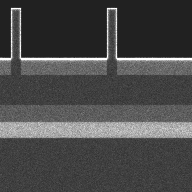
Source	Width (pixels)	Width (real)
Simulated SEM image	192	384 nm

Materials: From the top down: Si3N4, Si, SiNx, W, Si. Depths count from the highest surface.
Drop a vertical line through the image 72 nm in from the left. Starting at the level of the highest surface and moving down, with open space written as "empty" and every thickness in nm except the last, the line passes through empty 100, Si3N4 34, Si 60, SiNx 34, W 32, Si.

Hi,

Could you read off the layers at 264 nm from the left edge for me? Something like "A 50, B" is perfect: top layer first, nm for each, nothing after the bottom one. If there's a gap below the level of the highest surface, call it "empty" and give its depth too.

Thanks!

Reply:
empty 100, Si3N4 34, Si 60, SiNx 34, W 32, Si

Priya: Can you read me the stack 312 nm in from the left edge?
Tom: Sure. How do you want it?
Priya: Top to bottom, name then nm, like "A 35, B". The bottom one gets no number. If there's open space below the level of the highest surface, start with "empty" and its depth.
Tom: empty 100, Si3N4 34, Si 60, SiNx 34, W 32, Si